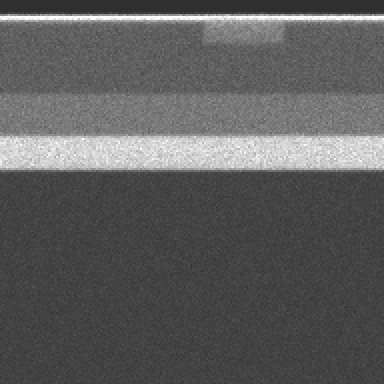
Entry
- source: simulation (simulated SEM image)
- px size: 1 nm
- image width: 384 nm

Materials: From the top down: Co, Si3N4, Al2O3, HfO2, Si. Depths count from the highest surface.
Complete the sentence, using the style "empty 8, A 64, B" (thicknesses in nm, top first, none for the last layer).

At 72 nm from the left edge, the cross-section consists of Si3N4 78, Al2O3 42, HfO2 34, Si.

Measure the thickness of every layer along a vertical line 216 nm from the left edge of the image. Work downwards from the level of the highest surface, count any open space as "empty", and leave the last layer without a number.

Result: Co 28, Si3N4 50, Al2O3 42, HfO2 34, Si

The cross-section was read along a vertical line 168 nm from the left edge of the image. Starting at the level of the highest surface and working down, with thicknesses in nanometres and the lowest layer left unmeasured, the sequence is Si3N4 78, Al2O3 42, HfO2 34, Si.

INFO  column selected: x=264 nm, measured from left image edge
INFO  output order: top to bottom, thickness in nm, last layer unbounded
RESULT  Co 28, Si3N4 50, Al2O3 42, HfO2 34, Si